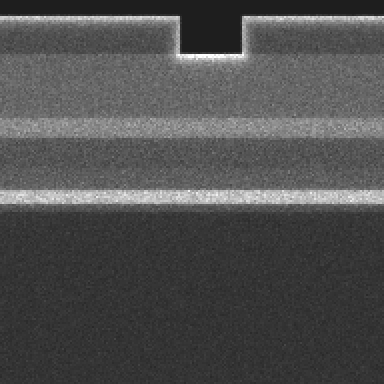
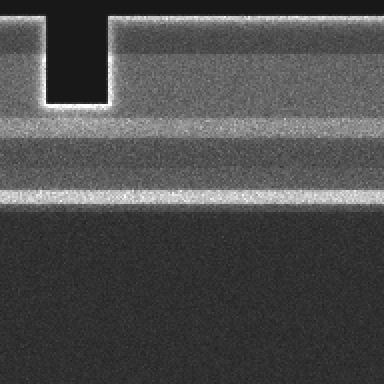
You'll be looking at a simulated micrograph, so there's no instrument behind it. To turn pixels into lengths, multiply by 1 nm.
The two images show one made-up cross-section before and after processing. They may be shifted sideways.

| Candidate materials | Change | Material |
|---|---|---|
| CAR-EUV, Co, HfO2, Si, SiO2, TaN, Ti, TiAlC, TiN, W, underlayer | removed | SiO2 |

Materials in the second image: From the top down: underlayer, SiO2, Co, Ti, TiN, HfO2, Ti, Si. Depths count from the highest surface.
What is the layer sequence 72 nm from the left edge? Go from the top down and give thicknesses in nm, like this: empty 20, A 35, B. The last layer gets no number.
empty 88, SiO2 14, Co 20, Ti 30, TiN 22, HfO2 14, Ti 8, Si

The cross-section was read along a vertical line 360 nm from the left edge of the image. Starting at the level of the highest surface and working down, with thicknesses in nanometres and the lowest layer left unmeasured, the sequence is underlayer 38, SiO2 64, Co 20, Ti 30, TiN 22, HfO2 14, Ti 8, Si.